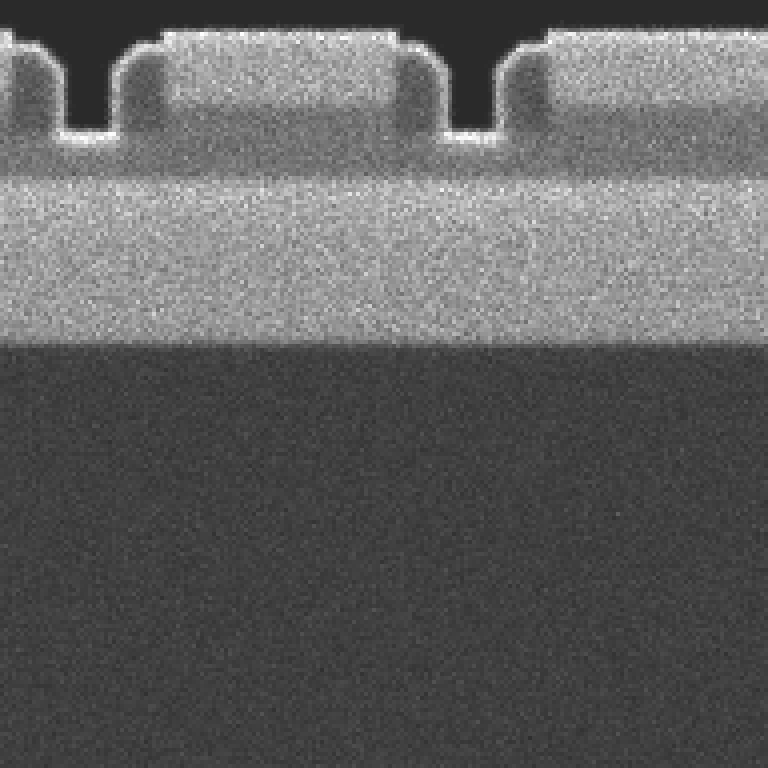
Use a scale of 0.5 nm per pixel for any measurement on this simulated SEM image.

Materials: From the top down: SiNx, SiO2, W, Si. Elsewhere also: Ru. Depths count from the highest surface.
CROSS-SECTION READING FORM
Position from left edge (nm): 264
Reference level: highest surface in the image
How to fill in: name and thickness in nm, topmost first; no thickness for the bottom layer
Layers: empty 6, SiNx 44, SiO2 24, W 82, Si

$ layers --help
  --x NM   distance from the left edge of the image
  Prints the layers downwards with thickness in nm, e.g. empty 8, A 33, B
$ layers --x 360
Ru 36, SiO2 38, W 82, Si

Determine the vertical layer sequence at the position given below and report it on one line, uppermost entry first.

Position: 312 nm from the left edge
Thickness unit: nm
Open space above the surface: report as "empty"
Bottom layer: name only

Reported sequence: Ru 36, SiO2 38, W 82, Si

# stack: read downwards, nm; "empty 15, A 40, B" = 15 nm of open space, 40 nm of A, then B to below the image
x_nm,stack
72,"empty 6, SiNx 44, SiO2 24, W 82, Si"